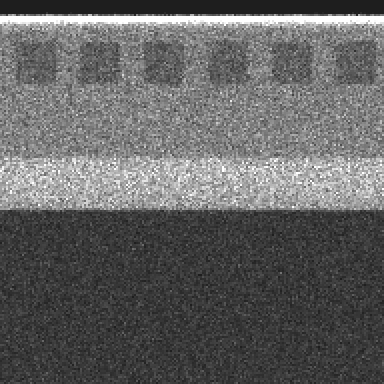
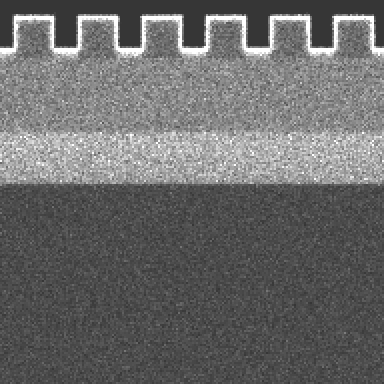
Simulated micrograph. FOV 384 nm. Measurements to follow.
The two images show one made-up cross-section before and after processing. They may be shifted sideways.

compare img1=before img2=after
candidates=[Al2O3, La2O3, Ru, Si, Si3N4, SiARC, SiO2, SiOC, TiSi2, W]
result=removed:SiO2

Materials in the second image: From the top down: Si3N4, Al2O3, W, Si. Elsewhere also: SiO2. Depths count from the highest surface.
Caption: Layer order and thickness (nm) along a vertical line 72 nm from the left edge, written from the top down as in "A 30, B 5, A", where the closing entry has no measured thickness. empty 32, SiO2 36, Al2O3 48, W 52, Si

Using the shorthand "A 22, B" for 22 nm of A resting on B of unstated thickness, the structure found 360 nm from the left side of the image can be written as Si3N4 42, Al2O3 74, W 52, Si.